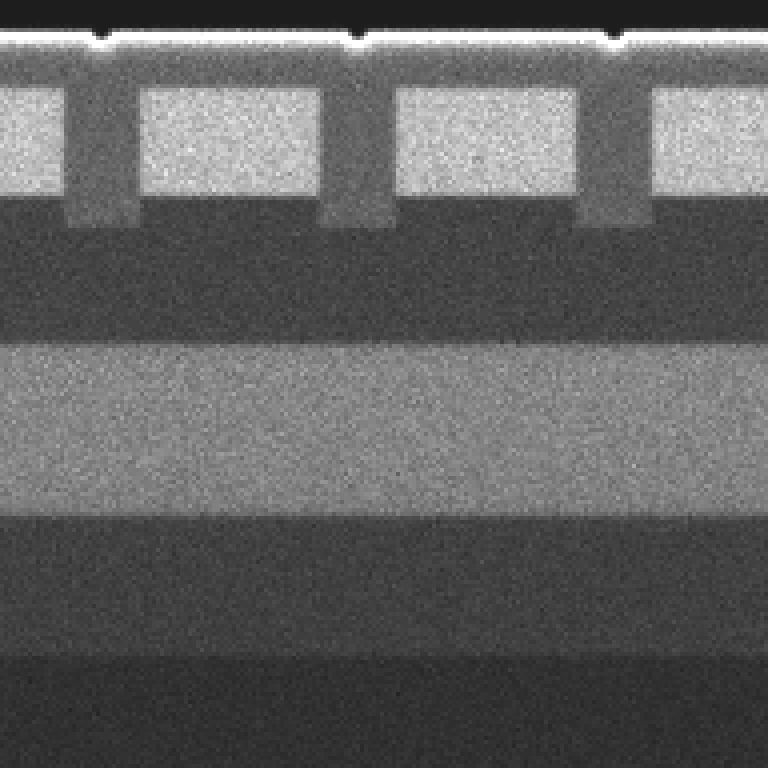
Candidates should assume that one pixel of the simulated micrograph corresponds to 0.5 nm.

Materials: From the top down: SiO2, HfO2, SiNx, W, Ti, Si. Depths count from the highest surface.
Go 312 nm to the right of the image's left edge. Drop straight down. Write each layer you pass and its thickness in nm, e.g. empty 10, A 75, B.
SiO2 98, SiNx 58, W 86, Ti 70, Si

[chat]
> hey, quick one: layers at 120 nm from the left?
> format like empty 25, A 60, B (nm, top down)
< SiO2 28, HfO2 54, SiNx 74, W 86, Ti 70, Si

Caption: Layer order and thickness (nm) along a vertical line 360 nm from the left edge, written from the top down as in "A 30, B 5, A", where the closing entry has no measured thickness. SiO2 28, HfO2 54, SiNx 74, W 86, Ti 70, Si